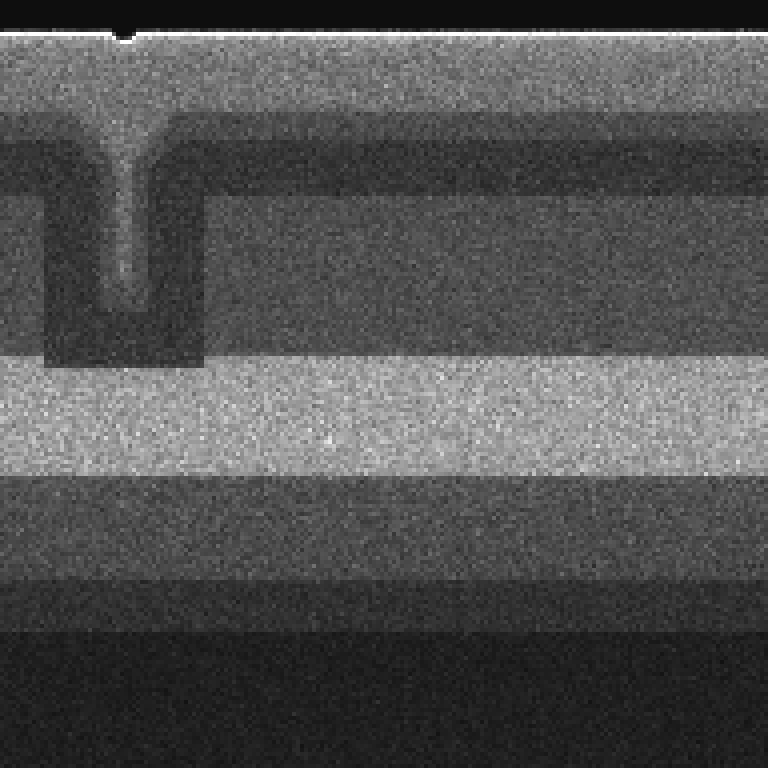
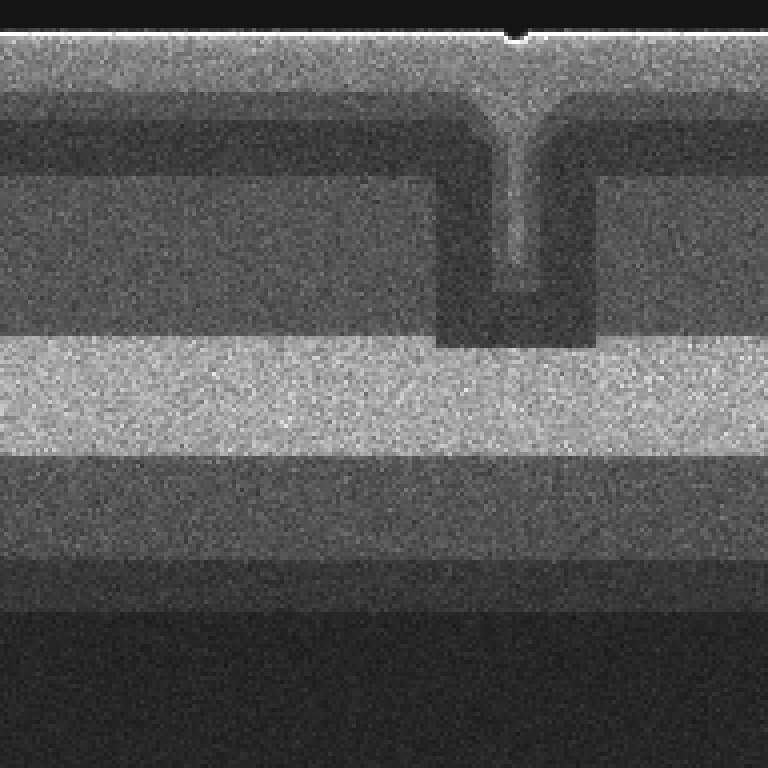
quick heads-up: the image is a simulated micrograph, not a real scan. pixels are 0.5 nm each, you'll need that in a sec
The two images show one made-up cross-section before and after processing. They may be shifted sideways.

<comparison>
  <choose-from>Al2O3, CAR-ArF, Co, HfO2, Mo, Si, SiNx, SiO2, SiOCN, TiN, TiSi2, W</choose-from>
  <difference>W removed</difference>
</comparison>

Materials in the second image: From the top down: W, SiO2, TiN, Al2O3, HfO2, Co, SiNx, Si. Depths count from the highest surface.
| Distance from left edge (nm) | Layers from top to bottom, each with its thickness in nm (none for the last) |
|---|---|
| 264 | W 52, SiO2 78, TiN 28, HfO2 54, Co 52, SiNx 26, Si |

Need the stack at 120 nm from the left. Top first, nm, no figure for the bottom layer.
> W 30, SiO2 14, TiN 28, Al2O3 80, HfO2 60, Co 52, SiNx 26, Si